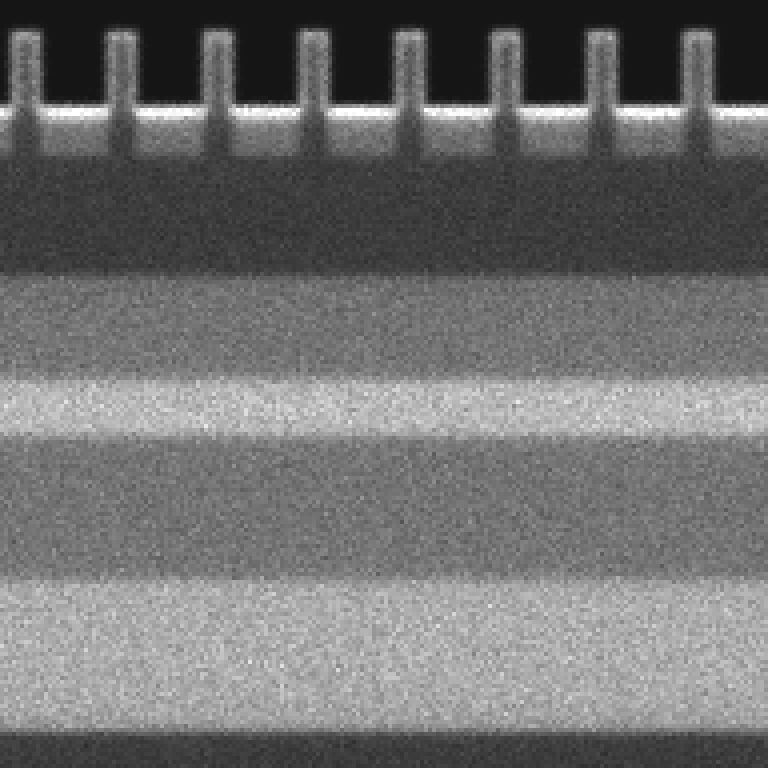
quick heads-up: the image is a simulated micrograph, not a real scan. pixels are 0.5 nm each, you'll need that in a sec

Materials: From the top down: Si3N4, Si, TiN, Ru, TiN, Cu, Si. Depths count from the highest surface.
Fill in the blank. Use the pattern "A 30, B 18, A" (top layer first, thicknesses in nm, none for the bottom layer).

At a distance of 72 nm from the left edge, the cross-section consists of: empty 38, Si3N4 24, Si 60, TiN 52, Ru 28, TiN 72, Cu 76, Si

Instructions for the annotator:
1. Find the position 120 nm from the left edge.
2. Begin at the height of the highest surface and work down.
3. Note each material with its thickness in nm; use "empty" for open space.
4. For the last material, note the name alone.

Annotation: empty 38, Si3N4 24, Si 60, TiN 52, Ru 28, TiN 72, Cu 76, Si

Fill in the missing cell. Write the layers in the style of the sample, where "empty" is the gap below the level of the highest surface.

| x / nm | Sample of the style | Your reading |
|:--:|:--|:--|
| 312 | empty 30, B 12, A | empty 38, Si3N4 24, Si 60, TiN 52, Ru 28, TiN 72, Cu 76, Si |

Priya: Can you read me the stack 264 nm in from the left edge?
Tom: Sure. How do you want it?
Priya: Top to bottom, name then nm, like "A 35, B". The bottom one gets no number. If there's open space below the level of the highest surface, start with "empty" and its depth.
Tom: empty 38, Si3N4 24, Si 60, TiN 52, Ru 28, TiN 72, Cu 76, Si